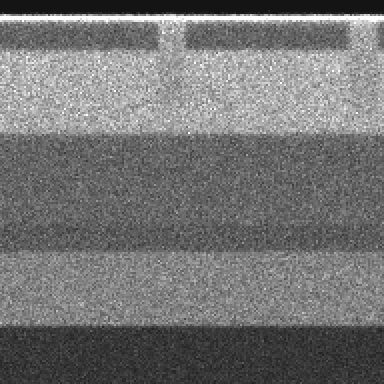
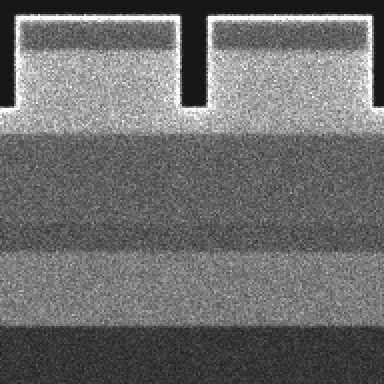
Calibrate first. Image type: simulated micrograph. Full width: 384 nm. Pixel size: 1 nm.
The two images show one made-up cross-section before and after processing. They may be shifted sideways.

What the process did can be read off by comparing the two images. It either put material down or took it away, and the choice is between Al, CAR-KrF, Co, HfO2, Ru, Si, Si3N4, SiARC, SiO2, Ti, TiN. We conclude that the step removed Co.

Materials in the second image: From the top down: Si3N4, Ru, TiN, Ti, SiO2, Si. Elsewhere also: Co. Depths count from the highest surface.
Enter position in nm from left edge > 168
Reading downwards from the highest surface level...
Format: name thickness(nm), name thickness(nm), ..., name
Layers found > Si3N4 34, Ru 84, TiN 90, Ti 28, SiO2 74, Si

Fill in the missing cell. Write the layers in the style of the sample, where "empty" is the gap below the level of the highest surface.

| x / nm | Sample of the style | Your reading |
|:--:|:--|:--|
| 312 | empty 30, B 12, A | Si3N4 34, Ru 84, TiN 90, Ti 28, SiO2 74, Si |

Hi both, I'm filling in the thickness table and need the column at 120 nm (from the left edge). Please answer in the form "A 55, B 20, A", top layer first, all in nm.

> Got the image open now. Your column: Si3N4 34, Ru 84, TiN 90, Ti 28, SiO2 74, Si